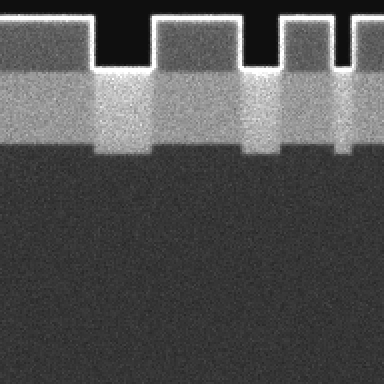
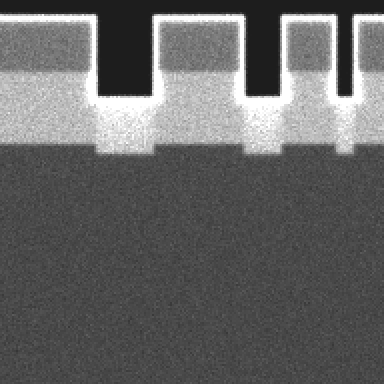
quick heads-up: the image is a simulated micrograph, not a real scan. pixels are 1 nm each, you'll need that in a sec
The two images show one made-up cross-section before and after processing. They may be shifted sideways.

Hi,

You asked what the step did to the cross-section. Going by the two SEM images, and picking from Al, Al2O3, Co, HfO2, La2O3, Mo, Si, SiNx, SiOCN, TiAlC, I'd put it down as Co, removed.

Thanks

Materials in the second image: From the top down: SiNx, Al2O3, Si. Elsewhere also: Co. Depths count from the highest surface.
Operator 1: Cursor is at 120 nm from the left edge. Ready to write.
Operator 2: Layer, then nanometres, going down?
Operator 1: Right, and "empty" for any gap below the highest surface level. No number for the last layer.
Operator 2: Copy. empty 82, Co 56, Si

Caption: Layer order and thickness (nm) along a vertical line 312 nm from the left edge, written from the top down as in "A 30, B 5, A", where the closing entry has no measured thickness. SiNx 56, Al2O3 72, Si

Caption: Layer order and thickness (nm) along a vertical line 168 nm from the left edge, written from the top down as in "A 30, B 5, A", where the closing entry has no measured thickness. SiNx 56, Al2O3 72, Si